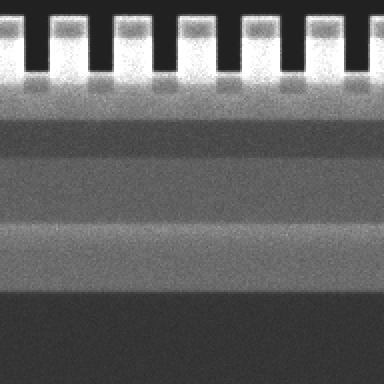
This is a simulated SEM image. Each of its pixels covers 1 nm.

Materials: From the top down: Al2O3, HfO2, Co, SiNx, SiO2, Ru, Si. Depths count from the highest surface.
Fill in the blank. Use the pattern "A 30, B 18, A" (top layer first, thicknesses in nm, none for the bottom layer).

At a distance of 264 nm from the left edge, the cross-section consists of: Al2O3 22, HfO2 46, Co 36, SiNx 38, SiO2 66, Ru 68, Si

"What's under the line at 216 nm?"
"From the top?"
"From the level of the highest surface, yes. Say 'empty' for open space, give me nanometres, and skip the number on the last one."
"empty 56, Al2O3 22, Co 26, SiNx 38, SiO2 66, Ru 68, Si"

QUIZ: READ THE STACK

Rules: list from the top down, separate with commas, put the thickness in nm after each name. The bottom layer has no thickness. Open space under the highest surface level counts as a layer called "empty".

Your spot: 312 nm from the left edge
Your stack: Al2O3 22, HfO2 46, Co 36, SiNx 38, SiO2 66, Ru 68, Si